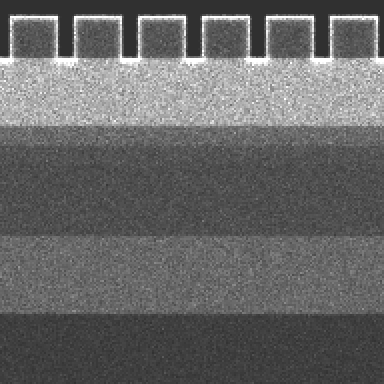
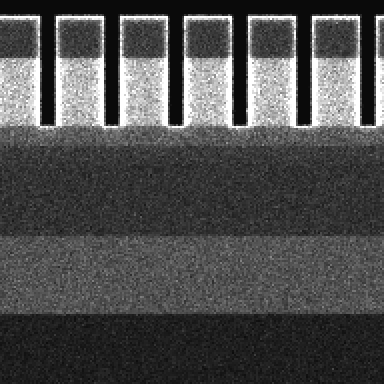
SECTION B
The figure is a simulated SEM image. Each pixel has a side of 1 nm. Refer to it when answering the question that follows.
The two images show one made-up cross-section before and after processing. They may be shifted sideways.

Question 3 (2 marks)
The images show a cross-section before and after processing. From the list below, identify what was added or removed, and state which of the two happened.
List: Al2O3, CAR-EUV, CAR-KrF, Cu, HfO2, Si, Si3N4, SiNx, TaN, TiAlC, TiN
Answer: HfO2 was removed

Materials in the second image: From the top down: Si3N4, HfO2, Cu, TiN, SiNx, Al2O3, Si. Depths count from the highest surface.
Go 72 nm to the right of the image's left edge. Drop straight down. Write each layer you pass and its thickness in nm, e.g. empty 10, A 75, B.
Si3N4 42, HfO2 68, Cu 20, TiN 18, SiNx 72, Al2O3 78, Si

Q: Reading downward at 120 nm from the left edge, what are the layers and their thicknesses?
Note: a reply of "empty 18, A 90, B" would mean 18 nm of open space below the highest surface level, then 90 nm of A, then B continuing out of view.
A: Si3N4 42, HfO2 68, Cu 20, TiN 18, SiNx 72, Al2O3 78, Si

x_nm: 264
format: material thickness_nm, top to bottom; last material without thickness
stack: Si3N4 42, HfO2 68, Cu 20, TiN 18, SiNx 72, Al2O3 78, Si